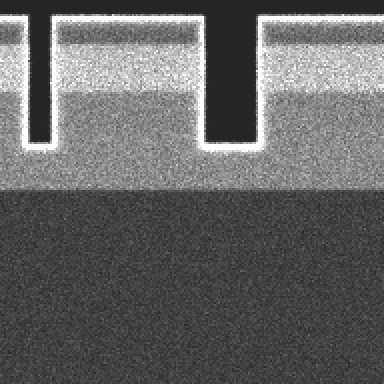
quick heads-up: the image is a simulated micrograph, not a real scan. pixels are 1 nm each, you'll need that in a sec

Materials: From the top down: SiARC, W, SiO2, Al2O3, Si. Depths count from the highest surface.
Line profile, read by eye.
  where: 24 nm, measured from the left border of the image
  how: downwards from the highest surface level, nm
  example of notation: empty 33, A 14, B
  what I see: SiARC 28, W 48, SiO2 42, Al2O3 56, Si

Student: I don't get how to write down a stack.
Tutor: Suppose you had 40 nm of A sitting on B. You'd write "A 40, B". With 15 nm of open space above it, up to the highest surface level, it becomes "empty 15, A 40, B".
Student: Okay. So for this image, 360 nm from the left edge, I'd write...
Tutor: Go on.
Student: SiARC 28, W 48, SiO2 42, Al2O3 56, Si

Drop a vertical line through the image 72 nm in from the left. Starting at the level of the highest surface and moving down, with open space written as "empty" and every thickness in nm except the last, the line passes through SiARC 28, W 48, SiO2 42, Al2O3 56, Si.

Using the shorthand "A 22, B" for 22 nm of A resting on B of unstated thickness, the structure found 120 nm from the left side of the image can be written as SiARC 28, W 48, SiO2 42, Al2O3 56, Si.